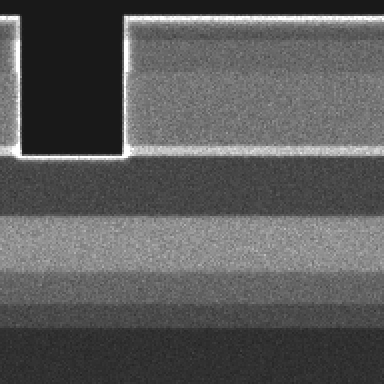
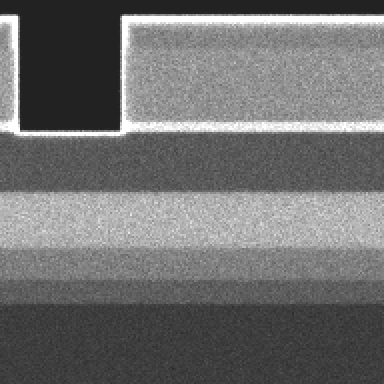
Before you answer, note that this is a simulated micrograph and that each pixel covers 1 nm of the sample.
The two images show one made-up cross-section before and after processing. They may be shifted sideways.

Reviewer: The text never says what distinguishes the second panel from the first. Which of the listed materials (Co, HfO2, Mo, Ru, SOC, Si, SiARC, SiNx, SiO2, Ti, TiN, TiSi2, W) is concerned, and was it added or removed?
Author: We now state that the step removed SOC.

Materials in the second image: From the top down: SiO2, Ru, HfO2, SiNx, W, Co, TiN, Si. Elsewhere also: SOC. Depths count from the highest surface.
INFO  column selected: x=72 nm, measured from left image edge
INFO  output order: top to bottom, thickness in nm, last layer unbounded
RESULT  empty 116, SiNx 60, W 56, Co 32, TiN 24, Si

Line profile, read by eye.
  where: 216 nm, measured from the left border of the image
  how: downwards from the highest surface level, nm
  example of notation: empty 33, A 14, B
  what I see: SiO2 32, Ru 74, HfO2 10, SiNx 60, W 56, Co 32, TiN 24, Si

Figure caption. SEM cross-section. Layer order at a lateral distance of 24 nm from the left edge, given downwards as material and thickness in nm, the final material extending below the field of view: empty 116, SiNx 60, W 56, Co 32, TiN 24, Si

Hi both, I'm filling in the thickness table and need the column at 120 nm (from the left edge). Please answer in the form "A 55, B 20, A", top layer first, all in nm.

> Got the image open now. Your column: empty 116, SiNx 60, W 56, Co 32, TiN 24, Si